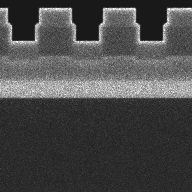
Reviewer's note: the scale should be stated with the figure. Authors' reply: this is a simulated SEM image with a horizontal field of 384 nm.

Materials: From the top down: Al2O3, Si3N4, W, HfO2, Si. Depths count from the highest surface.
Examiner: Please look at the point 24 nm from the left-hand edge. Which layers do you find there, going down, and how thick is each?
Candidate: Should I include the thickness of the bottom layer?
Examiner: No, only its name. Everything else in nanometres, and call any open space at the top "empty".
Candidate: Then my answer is empty 66, Al2O3 38, W 42, HfO2 34, Si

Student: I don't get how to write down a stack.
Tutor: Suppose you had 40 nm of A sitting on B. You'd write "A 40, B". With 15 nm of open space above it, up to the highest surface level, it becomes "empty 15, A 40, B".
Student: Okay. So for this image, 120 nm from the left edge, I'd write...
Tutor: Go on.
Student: Al2O3 38, Si3N4 58, W 50, HfO2 34, Si